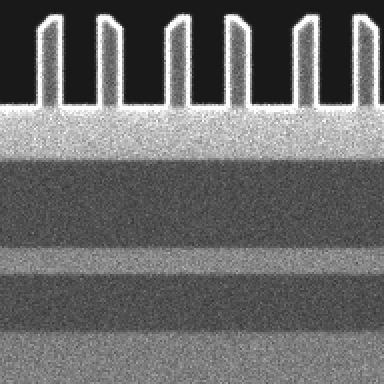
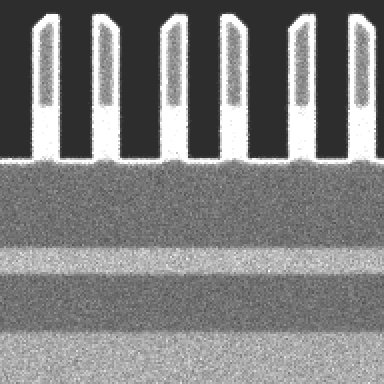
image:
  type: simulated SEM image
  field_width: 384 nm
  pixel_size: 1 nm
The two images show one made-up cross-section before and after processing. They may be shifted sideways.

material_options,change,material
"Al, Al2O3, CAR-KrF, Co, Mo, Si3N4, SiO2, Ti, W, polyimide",removed,W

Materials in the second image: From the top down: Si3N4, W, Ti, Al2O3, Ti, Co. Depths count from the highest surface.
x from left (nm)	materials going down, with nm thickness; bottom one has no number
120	empty 144, Ti 88, Al2O3 26, Ti 58, Co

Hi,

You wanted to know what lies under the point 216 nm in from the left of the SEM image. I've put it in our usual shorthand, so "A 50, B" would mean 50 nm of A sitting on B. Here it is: empty 144, Ti 88, Al2O3 26, Ti 58, Co